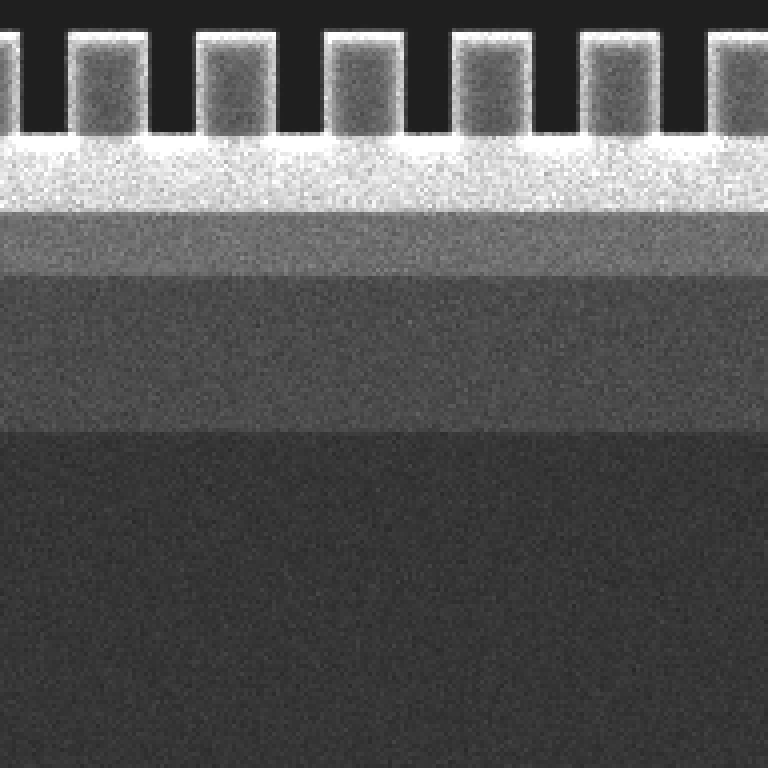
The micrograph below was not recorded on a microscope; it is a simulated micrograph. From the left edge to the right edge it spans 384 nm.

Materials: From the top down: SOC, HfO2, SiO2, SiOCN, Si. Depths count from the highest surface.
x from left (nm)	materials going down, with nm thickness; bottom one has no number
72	SOC 52, HfO2 38, SiO2 32, SiOCN 78, Si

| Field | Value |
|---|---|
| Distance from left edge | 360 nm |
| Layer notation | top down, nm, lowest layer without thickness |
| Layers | SOC 52, HfO2 38, SiO2 32, SiOCN 78, Si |